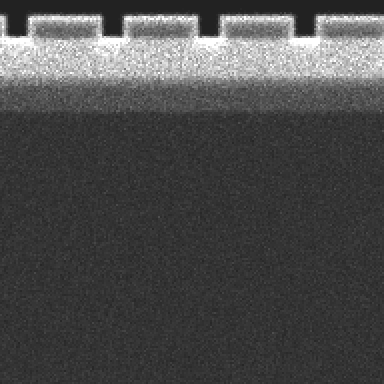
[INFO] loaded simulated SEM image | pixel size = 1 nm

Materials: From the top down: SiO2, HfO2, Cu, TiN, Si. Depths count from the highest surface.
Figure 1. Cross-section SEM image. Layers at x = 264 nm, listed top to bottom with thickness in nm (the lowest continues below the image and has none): SiO2 22, HfO2 40, Cu 8, TiN 26, Si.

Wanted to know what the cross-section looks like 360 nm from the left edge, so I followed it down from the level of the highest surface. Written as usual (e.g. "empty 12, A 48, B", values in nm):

SiO2 22, HfO2 40, Cu 8, TiN 26, Si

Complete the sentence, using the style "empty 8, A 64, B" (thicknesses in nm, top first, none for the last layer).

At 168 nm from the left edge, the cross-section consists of SiO2 22, HfO2 40, Cu 8, TiN 26, Si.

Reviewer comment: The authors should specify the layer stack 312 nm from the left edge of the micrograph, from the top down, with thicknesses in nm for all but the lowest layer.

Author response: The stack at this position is empty 22, HfO2 40, Cu 8, TiN 26, Si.